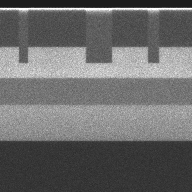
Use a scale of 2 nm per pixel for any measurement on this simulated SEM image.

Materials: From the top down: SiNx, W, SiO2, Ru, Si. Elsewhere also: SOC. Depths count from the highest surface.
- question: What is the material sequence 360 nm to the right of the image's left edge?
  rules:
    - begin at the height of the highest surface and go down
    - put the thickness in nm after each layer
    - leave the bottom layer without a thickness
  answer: SiNx 78, W 62, SiO2 54, Ru 72, Si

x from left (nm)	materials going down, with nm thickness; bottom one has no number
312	SOC 110, W 30, SiO2 54, Ru 72, Si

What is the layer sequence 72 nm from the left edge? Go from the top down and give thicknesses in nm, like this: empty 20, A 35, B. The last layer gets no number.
SiNx 78, W 62, SiO2 54, Ru 72, Si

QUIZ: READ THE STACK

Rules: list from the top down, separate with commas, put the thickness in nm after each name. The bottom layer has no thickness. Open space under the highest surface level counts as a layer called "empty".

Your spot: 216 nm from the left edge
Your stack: SOC 110, W 30, SiO2 54, Ru 72, Si